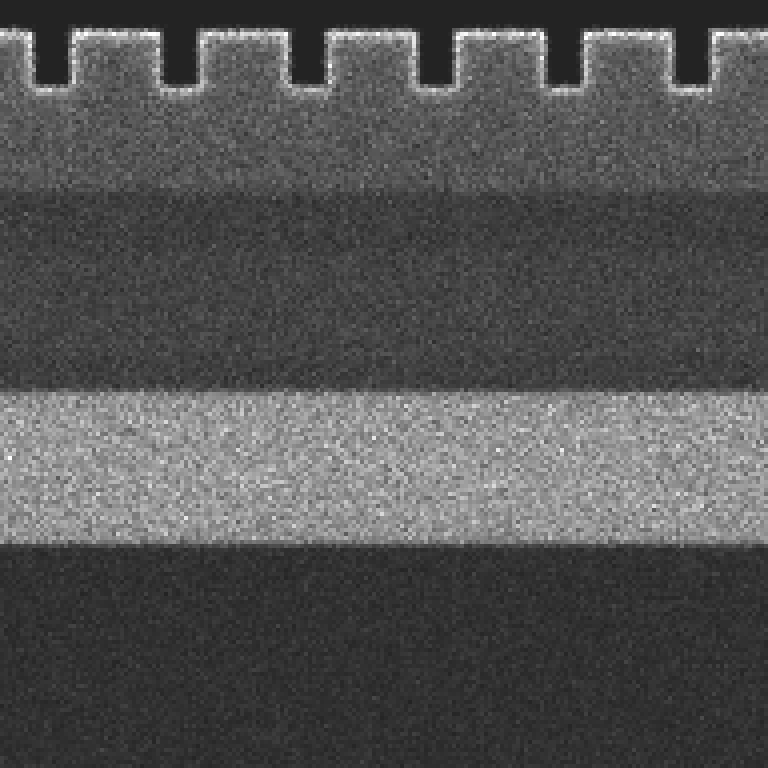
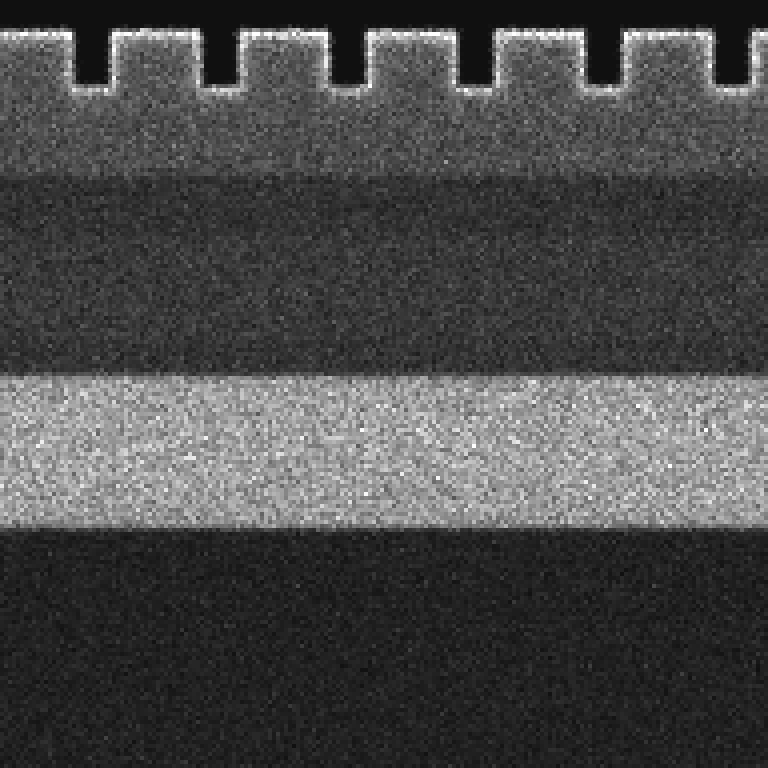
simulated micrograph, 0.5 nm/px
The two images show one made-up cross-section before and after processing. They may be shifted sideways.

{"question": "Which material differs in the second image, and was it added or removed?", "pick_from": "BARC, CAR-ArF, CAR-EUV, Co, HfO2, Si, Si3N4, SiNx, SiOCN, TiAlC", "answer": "Co, removed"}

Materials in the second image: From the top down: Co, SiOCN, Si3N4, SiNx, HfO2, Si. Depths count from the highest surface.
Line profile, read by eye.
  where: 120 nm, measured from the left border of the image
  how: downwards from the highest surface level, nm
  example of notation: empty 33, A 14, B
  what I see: Co 72, SiOCN 30, Si3N4 52, SiNx 18, HfO2 76, Si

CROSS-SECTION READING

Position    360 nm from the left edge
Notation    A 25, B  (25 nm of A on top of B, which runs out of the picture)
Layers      empty 28, Co 44, SiOCN 30, Si3N4 52, SiNx 18, HfO2 76, Si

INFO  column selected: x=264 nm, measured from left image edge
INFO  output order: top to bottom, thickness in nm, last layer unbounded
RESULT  Co 72, SiOCN 30, Si3N4 52, SiNx 18, HfO2 76, Si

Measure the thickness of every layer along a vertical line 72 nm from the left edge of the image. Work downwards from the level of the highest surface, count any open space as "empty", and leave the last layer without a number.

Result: Co 72, SiOCN 30, Si3N4 52, SiNx 18, HfO2 76, Si